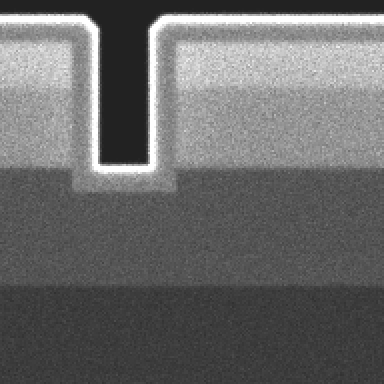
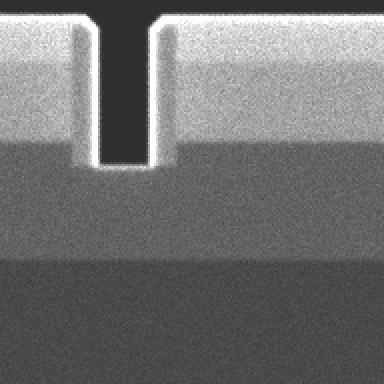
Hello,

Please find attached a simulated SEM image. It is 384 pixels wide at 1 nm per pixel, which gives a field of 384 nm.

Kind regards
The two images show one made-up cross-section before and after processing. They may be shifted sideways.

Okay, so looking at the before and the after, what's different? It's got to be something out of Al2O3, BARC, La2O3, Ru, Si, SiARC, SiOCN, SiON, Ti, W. Al2O3, removed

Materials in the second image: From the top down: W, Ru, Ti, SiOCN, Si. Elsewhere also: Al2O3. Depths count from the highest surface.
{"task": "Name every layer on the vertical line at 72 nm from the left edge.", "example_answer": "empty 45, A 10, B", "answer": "Al2O3 150, Ti 62, SiOCN 32, Si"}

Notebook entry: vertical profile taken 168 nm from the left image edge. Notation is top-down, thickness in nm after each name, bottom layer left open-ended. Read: Al2O3 150, Ti 62, SiOCN 32, Si